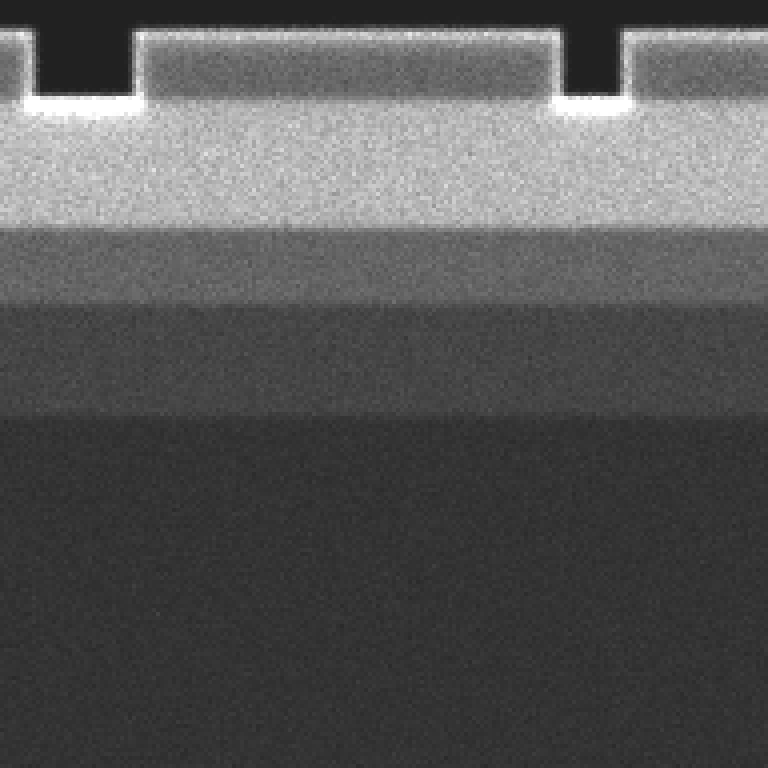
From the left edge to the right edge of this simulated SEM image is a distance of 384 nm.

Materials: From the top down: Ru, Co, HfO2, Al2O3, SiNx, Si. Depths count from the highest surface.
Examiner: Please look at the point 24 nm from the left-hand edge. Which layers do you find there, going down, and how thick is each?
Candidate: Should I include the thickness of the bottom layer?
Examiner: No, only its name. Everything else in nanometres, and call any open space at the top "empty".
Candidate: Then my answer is empty 34, HfO2 64, Al2O3 38, SiNx 56, Si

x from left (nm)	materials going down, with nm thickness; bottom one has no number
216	Ru 10, Co 24, HfO2 64, Al2O3 38, SiNx 56, Si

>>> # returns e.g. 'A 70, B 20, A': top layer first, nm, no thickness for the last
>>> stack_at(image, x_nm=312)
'Ru 10, Co 24, HfO2 64, Al2O3 38, SiNx 56, Si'